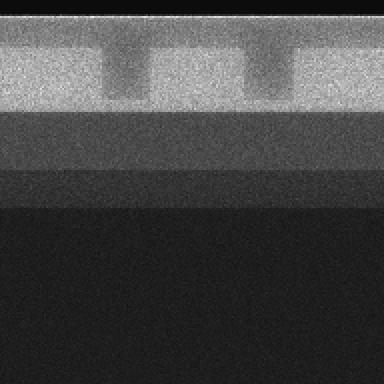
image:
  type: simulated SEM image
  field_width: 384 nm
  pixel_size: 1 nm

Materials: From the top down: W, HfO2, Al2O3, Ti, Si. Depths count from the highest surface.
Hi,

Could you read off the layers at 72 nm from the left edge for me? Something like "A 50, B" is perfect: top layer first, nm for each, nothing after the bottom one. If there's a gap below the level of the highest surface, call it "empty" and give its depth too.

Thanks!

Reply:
W 32, HfO2 64, Al2O3 58, Ti 38, Si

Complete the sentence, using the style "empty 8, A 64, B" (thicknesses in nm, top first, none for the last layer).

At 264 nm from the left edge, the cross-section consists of W 84, HfO2 12, Al2O3 58, Ti 38, Si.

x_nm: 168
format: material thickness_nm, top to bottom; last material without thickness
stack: W 32, HfO2 64, Al2O3 58, Ti 38, Si